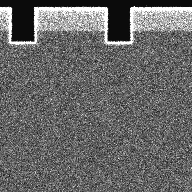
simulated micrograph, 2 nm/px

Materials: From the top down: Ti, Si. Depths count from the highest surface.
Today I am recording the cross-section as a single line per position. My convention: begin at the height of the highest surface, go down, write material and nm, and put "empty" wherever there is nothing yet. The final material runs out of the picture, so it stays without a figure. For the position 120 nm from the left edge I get Ti 46, Si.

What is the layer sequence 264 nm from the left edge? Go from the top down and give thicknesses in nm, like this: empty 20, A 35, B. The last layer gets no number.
Ti 46, Si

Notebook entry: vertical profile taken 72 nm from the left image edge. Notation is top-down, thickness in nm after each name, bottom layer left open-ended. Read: Ti 46, Si